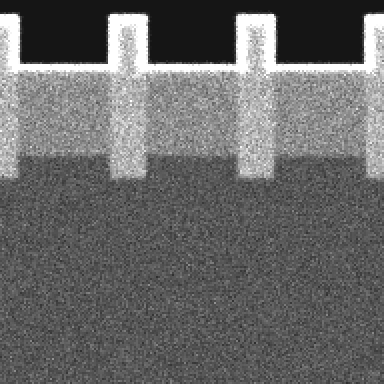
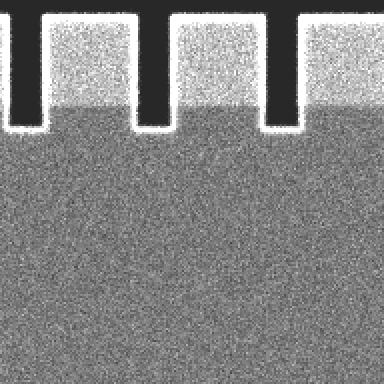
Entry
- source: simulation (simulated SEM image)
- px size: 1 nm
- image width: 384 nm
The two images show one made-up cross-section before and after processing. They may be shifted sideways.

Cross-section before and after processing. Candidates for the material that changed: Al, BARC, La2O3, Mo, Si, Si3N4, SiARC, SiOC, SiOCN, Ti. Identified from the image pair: SiARC (removed).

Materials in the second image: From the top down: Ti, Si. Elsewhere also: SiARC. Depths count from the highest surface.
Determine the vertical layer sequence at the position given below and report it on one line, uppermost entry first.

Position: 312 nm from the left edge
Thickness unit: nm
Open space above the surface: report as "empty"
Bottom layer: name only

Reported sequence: Ti 90, Si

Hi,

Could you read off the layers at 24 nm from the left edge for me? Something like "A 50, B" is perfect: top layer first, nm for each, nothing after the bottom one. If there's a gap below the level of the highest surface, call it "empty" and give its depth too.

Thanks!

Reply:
empty 112, Si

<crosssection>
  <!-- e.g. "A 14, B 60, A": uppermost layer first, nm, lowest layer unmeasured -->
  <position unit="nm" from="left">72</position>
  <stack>Ti 90, Si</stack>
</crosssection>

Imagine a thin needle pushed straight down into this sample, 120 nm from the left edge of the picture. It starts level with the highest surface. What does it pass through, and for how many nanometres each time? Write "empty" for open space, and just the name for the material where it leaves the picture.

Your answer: Ti 90, Si